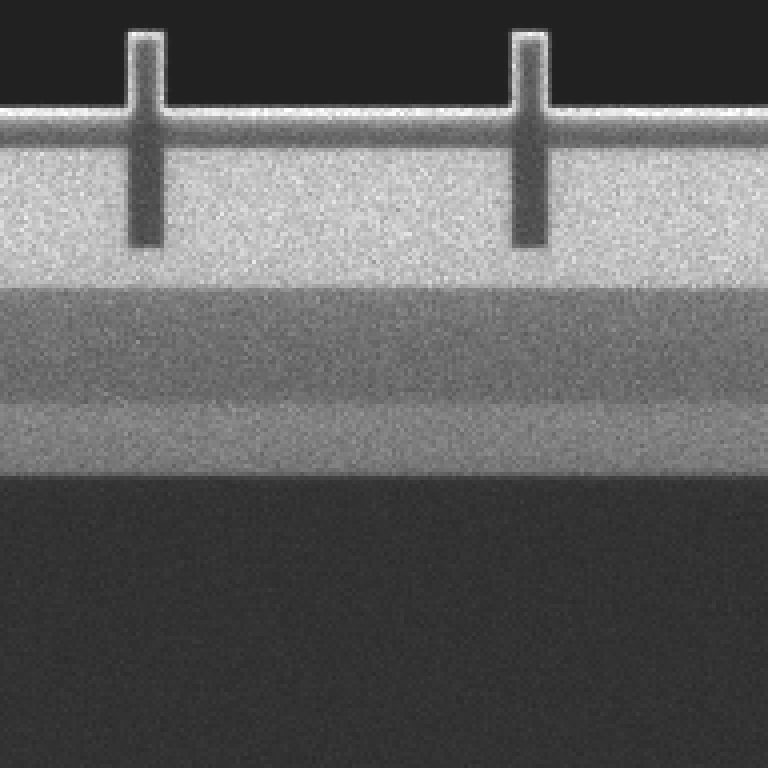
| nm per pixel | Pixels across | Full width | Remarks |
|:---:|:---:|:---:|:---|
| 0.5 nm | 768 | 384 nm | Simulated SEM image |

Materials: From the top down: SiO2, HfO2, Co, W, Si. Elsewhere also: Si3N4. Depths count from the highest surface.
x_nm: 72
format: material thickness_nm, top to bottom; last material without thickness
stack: Si3N4 108, HfO2 20, Co 58, W 36, Si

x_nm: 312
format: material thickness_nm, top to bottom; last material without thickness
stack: empty 38, SiO2 20, HfO2 70, Co 58, W 36, Si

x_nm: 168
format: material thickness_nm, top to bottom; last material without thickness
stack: empty 38, SiO2 20, HfO2 70, Co 58, W 36, Si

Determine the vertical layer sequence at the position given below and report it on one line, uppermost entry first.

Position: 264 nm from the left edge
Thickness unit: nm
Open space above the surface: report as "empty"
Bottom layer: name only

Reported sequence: Si3N4 108, HfO2 20, Co 58, W 36, Si